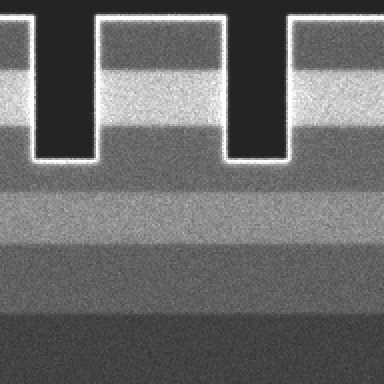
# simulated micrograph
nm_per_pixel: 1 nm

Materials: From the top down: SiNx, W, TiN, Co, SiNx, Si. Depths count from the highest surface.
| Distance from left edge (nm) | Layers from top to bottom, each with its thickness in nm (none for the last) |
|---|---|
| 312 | SiNx 54, W 56, TiN 66, Co 52, SiNx 70, Si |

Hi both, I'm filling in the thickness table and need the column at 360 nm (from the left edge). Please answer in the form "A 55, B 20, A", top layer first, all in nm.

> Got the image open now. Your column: SiNx 54, W 56, TiN 66, Co 52, SiNx 70, Si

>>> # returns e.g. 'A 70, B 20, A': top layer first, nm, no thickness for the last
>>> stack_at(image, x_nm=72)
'empty 144, TiN 32, Co 52, SiNx 70, Si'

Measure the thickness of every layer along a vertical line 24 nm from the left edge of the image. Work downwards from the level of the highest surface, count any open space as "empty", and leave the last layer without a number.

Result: SiNx 54, W 56, TiN 66, Co 52, SiNx 70, Si